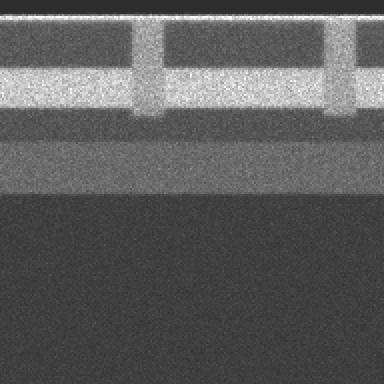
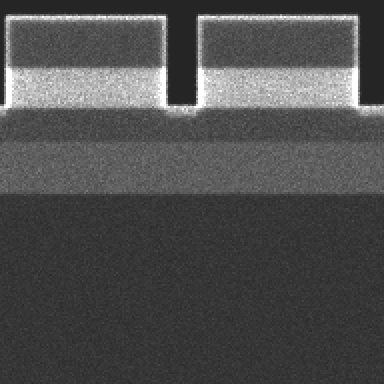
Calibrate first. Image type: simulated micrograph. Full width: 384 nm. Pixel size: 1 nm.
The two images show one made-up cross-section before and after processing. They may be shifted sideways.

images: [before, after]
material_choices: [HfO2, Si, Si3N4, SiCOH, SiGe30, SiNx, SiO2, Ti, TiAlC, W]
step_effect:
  removed: W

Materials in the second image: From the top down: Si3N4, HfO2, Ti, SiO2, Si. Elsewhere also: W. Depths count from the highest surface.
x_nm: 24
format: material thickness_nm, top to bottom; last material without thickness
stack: Si3N4 52, HfO2 40, Ti 34, SiO2 52, Si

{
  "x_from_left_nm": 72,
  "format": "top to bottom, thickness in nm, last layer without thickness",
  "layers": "Si3N4 52, HfO2 40, Ti 34, SiO2 52, Si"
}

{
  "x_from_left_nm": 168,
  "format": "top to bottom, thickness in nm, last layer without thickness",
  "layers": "empty 90, W 10, Ti 26, SiO2 52, Si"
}